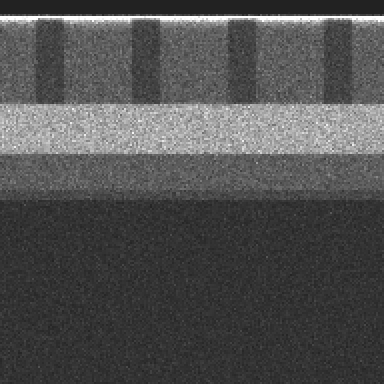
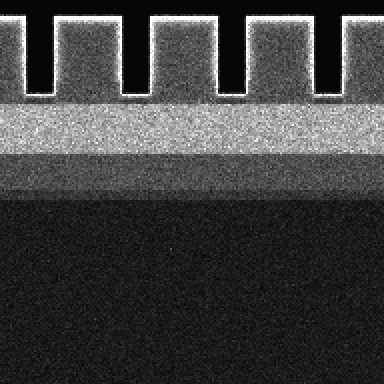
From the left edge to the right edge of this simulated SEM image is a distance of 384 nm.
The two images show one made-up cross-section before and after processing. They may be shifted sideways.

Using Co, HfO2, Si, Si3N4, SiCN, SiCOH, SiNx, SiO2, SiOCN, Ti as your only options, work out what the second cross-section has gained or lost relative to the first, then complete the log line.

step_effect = removed SiNx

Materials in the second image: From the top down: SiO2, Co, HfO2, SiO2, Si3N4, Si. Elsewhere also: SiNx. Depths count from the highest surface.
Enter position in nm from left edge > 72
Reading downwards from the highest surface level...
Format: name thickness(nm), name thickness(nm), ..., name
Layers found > SiO2 64, Co 24, HfO2 50, SiO2 36, Si3N4 10, Si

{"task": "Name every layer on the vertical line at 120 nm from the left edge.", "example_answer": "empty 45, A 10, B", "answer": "SiO2 64, Co 24, HfO2 50, SiO2 36, Si3N4 10, Si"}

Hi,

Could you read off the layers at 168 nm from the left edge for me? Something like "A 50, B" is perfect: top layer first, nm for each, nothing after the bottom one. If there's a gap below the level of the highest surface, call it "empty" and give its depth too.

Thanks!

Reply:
SiO2 64, Co 24, HfO2 50, SiO2 36, Si3N4 10, Si